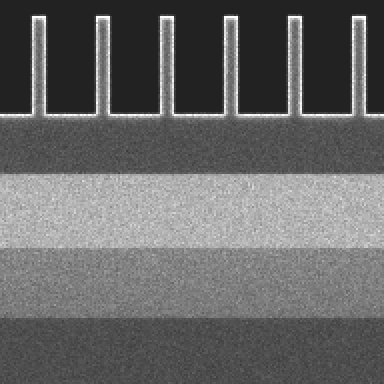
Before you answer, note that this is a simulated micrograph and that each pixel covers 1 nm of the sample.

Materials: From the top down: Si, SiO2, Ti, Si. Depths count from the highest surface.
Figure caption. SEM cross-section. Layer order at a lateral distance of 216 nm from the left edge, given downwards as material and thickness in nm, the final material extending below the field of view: empty 98, Si 60, SiO2 74, Ti 70, Si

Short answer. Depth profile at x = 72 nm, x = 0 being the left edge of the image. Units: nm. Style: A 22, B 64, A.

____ empty 98, Si 60, SiO2 74, Ti 70, Si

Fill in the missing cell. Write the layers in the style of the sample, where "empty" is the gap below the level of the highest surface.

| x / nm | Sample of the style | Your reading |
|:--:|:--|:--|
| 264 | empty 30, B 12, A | empty 98, Si 60, SiO2 74, Ti 70, Si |